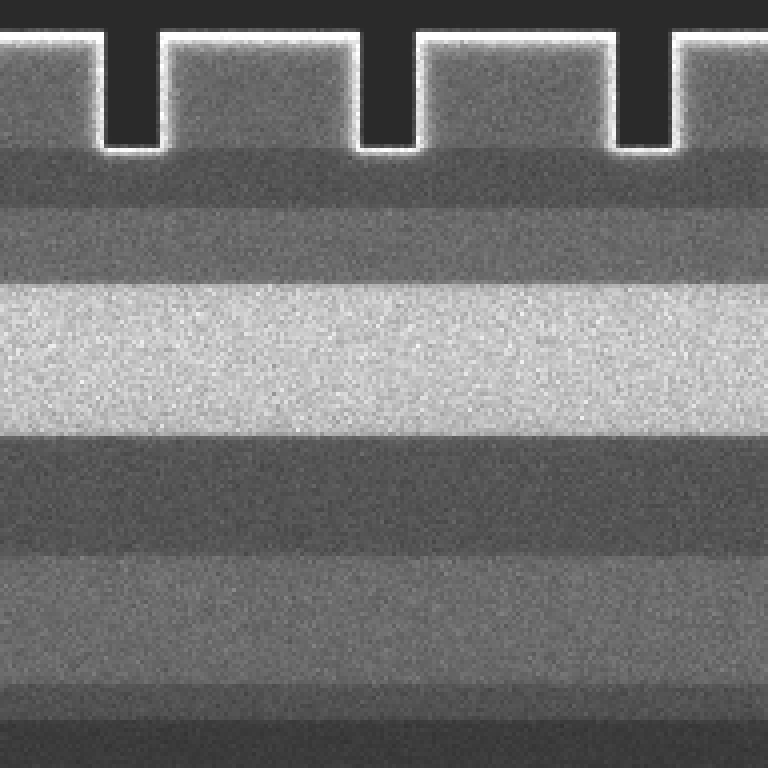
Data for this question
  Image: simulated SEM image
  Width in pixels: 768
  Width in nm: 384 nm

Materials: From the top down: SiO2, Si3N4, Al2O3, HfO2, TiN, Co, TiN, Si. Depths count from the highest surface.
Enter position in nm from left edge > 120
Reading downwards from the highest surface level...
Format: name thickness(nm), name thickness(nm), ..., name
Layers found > SiO2 58, Si3N4 30, Al2O3 38, HfO2 76, TiN 60, Co 64, TiN 18, Si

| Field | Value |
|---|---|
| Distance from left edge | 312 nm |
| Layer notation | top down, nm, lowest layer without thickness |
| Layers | empty 58, Si3N4 30, Al2O3 38, HfO2 76, TiN 60, Co 64, TiN 18, Si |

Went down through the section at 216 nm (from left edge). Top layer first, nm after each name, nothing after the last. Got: SiO2 58, Si3N4 30, Al2O3 38, HfO2 76, TiN 60, Co 64, TiN 18, Si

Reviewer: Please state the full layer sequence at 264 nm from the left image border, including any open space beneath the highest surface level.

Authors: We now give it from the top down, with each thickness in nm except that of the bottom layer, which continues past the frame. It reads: SiO2 58, Si3N4 30, Al2O3 38, HfO2 76, TiN 60, Co 64, TiN 18, Si